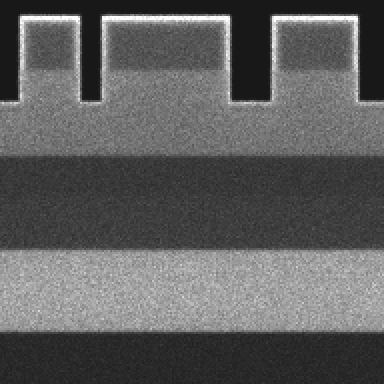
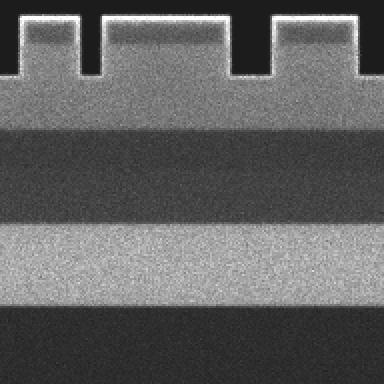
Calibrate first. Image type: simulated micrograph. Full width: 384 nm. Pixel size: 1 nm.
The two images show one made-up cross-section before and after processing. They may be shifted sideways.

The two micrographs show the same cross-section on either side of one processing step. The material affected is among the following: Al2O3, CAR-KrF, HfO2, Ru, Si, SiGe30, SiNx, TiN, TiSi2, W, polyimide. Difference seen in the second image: Al2O3 removed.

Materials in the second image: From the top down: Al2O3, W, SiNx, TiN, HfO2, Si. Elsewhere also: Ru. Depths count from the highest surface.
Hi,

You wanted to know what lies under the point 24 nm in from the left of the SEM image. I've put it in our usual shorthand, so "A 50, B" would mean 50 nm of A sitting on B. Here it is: Al2O3 28, W 86, SiNx 40, TiN 54, HfO2 82, Si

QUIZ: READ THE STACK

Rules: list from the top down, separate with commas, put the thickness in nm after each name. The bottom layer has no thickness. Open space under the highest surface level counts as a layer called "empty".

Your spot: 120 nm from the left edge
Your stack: Al2O3 28, W 86, SiNx 40, TiN 54, HfO2 82, Si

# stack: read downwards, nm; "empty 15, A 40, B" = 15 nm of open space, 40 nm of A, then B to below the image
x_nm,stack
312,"Al2O3 28, W 86, SiNx 40, TiN 54, HfO2 82, Si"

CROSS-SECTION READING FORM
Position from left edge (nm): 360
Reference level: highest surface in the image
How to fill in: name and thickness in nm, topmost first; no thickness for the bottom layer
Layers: empty 60, Ru 10, W 44, SiNx 40, TiN 54, HfO2 82, Si